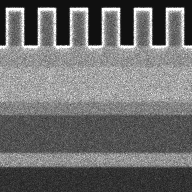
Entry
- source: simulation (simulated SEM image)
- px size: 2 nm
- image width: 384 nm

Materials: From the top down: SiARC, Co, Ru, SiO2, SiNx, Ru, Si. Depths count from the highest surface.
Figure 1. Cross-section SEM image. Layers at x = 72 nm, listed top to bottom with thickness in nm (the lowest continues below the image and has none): empty 76, Co 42, Ru 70, SiO2 26, SiNx 76, Ru 28, Si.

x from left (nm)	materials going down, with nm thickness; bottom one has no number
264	empty 76, Co 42, Ru 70, SiO2 26, SiNx 76, Ru 28, Si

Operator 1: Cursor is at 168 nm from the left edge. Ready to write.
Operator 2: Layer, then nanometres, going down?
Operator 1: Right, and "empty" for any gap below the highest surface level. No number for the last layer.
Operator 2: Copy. SiARC 76, Co 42, Ru 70, SiO2 26, SiNx 76, Ru 28, Si